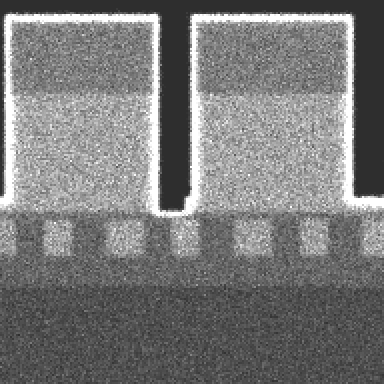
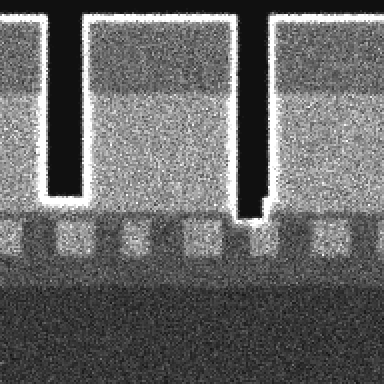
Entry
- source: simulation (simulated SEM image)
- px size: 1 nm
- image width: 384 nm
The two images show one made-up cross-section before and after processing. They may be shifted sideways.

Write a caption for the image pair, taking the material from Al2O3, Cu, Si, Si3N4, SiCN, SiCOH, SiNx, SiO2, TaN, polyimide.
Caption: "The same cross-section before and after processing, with SiNx removed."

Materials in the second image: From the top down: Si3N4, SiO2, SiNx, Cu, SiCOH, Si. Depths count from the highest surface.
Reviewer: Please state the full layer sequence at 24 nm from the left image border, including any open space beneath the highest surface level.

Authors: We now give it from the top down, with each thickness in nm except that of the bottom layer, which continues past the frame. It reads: Si3N4 78, SiO2 118, SiNx 8, SiCOH 66, Si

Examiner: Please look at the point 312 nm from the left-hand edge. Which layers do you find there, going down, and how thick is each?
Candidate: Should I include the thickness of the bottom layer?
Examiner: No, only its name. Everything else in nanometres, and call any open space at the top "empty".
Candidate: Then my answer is Si3N4 78, SiO2 118, SiNx 8, Cu 36, SiCOH 30, Si